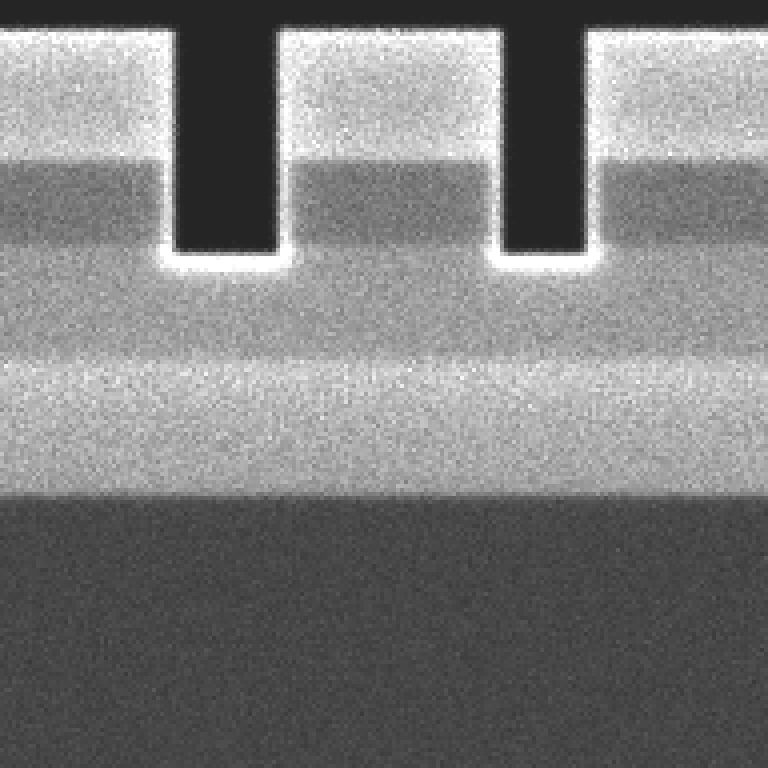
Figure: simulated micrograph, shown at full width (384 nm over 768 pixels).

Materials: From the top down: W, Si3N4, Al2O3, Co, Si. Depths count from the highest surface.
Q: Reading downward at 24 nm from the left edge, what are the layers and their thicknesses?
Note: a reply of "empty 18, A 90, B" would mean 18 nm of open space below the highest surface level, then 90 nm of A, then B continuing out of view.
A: W 64, Si3N4 42, Al2O3 58, Co 68, Si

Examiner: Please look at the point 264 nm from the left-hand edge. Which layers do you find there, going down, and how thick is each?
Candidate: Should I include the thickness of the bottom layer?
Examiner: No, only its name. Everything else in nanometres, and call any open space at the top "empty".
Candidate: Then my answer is empty 112, Al2O3 52, Co 68, Si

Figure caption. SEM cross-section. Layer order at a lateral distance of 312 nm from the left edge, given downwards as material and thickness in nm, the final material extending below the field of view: W 64, Si3N4 42, Al2O3 58, Co 68, Si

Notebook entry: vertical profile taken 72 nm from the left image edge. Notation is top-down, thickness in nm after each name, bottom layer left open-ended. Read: W 64, Si3N4 42, Al2O3 58, Co 68, Si